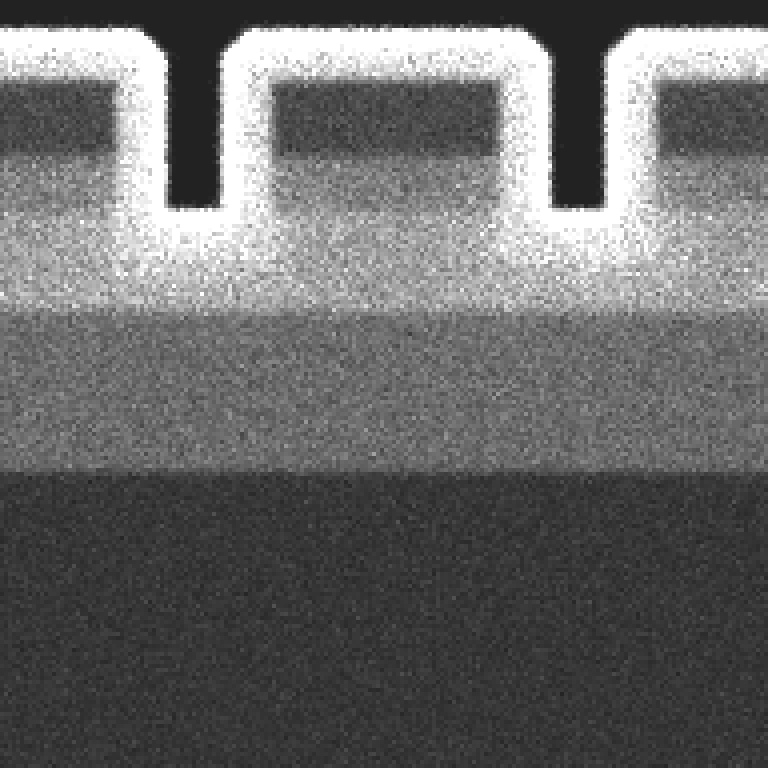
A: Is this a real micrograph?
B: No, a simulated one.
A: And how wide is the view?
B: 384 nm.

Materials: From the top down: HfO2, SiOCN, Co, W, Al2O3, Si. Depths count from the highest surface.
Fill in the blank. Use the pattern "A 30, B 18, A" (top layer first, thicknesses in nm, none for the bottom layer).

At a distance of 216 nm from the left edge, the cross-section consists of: HfO2 24, SiOCN 38, Co 28, W 50, Al2O3 80, Si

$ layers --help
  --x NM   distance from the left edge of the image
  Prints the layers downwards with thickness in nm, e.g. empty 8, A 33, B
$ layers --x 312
empty 4, HfO2 110, W 26, Al2O3 80, Si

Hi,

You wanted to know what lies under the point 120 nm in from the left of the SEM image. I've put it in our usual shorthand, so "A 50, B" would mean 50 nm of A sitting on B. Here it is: empty 4, HfO2 110, W 26, Al2O3 80, Si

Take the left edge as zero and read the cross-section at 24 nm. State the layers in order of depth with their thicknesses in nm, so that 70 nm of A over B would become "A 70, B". HfO2 24, SiOCN 38, Co 28, W 50, Al2O3 80, Si